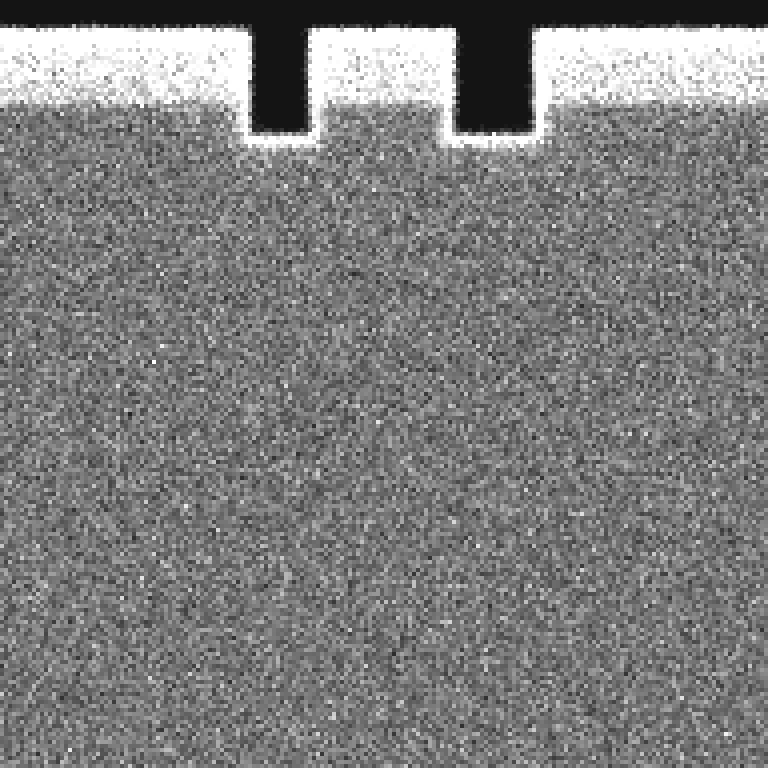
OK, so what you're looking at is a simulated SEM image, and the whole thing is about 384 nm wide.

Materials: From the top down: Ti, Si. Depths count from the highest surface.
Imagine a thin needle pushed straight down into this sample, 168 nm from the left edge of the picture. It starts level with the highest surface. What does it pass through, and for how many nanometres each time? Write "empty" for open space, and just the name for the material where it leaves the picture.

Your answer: Ti 36, Si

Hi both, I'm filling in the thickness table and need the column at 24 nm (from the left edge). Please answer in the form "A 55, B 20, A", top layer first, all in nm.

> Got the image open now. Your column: Ti 36, Si